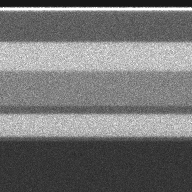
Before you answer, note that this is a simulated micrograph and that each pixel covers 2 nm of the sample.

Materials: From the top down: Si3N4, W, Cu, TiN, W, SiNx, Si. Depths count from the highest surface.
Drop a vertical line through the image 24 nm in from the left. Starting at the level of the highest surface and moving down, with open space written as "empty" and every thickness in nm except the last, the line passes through Si3N4 68, W 58, Cu 70, TiN 16, W 46, SiNx 8, Si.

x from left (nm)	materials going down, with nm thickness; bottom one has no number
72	Si3N4 68, W 58, Cu 70, TiN 16, W 46, SiNx 8, Si